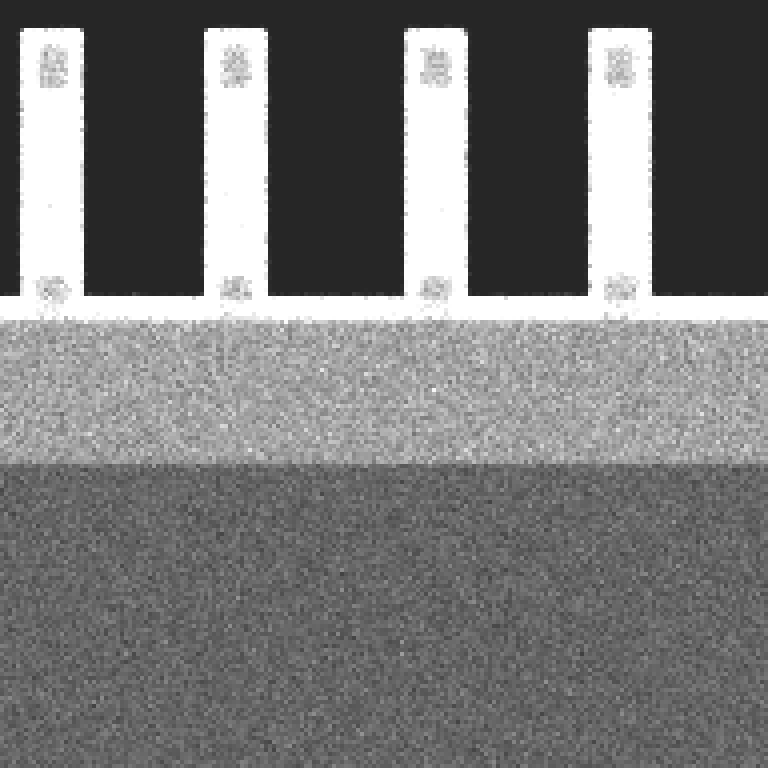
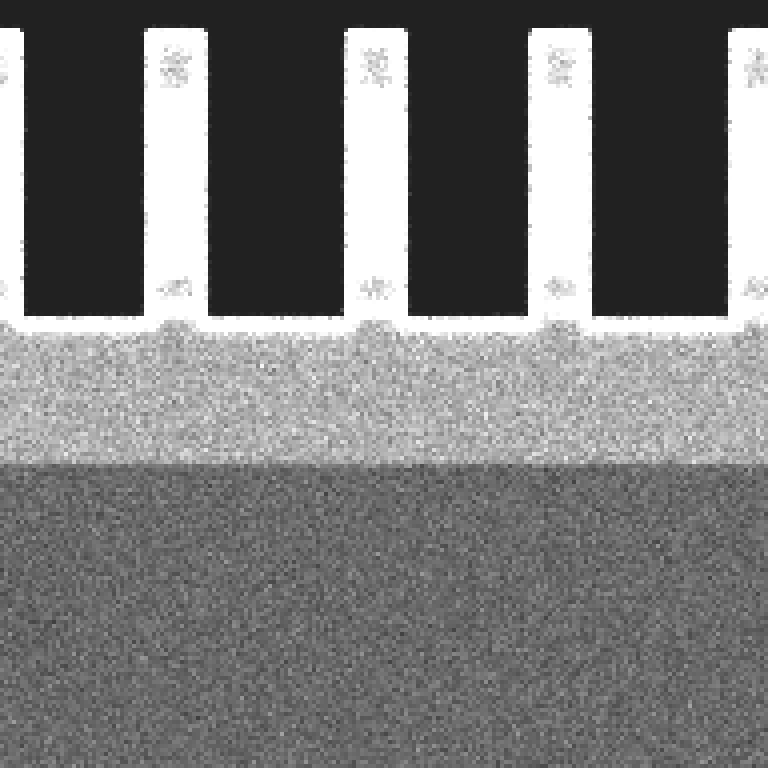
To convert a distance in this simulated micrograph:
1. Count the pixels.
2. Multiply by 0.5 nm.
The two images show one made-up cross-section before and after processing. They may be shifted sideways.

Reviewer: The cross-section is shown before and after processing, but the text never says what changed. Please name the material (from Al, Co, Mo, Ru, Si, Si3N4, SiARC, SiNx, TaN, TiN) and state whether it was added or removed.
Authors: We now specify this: Co, removed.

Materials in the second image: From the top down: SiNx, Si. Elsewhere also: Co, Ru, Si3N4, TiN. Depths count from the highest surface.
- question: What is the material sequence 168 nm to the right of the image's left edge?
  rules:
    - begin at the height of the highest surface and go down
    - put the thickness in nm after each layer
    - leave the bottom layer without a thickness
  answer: empty 144, SiNx 72, Si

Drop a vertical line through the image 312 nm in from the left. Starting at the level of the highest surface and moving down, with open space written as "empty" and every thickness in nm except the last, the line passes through empty 144, SiNx 72, Si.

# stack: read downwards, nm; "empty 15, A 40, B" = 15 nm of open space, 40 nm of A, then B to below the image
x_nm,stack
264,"empty 144, SiNx 72, Si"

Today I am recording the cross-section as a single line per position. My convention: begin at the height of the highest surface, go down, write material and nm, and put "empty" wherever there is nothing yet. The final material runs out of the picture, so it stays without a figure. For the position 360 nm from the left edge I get empty 144, SiNx 72, Si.